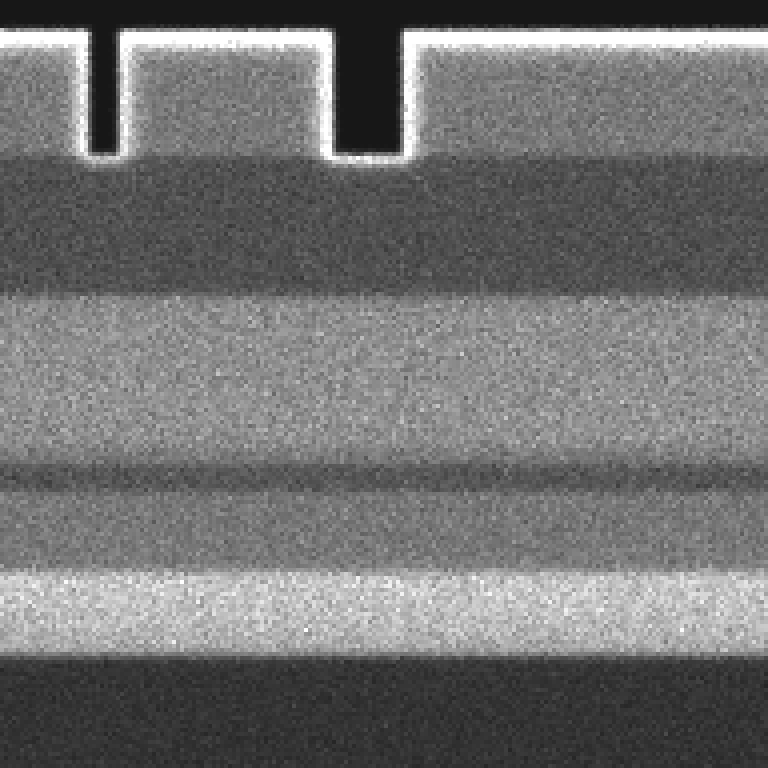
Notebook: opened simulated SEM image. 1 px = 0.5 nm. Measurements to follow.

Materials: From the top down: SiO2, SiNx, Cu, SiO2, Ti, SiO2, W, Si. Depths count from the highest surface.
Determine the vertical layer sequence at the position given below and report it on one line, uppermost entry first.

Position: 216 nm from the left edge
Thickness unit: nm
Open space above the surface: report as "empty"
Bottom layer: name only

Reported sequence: SiO2 62, SiNx 70, Cu 76, SiO2 8, Ti 14, SiO2 40, W 42, Si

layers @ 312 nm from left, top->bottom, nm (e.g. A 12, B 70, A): SiO2 62, SiNx 70, Cu 76, SiO2 8, Ti 14, SiO2 40, W 42, Si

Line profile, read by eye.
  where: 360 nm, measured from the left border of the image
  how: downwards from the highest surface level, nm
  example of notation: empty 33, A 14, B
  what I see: SiO2 62, SiNx 70, Cu 76, SiO2 8, Ti 14, SiO2 40, W 42, Si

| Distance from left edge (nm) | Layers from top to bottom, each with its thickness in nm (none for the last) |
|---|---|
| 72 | SiO2 62, SiNx 70, Cu 76, SiO2 8, Ti 14, SiO2 40, W 42, Si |